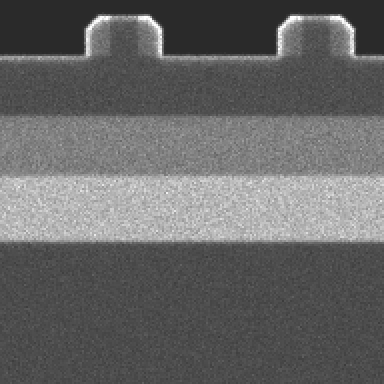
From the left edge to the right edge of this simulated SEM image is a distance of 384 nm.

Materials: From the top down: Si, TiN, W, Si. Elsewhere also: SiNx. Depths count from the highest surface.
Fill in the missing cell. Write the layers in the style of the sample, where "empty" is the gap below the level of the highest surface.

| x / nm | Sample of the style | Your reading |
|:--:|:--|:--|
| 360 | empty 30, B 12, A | empty 40, Si 60, TiN 60, W 66, Si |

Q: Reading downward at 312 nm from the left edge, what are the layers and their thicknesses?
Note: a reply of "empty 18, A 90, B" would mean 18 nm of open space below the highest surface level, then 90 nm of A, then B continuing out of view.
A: Si 100, TiN 60, W 66, Si